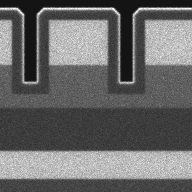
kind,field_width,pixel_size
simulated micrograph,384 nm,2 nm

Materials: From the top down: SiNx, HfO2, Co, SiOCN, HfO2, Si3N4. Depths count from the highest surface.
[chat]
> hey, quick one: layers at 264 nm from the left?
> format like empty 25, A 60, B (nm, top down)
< empty 148, SiNx 24, Co 28, SiOCN 86, HfO2 56, Si3N4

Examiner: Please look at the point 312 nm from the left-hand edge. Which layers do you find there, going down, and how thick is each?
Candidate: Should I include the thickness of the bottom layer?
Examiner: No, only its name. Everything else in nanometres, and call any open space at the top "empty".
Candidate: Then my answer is SiNx 24, HfO2 90, Co 86, SiOCN 86, HfO2 56, Si3N4